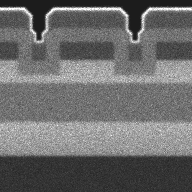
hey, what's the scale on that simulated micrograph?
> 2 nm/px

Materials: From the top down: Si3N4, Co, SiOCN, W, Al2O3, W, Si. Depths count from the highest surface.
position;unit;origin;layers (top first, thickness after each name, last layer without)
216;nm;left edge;Si3N4 40, Co 28, SiOCN 36, W 46, Al2O3 78, W 68, Si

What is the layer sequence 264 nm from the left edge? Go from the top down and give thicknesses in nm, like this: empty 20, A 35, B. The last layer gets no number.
empty 66, Si3N4 40, Co 28, W 16, Al2O3 78, W 68, Si